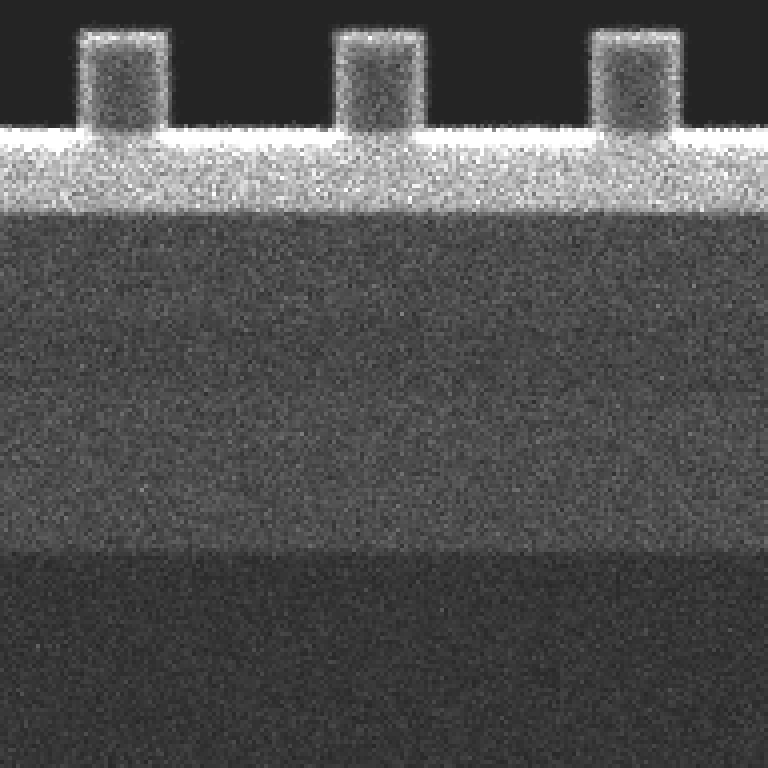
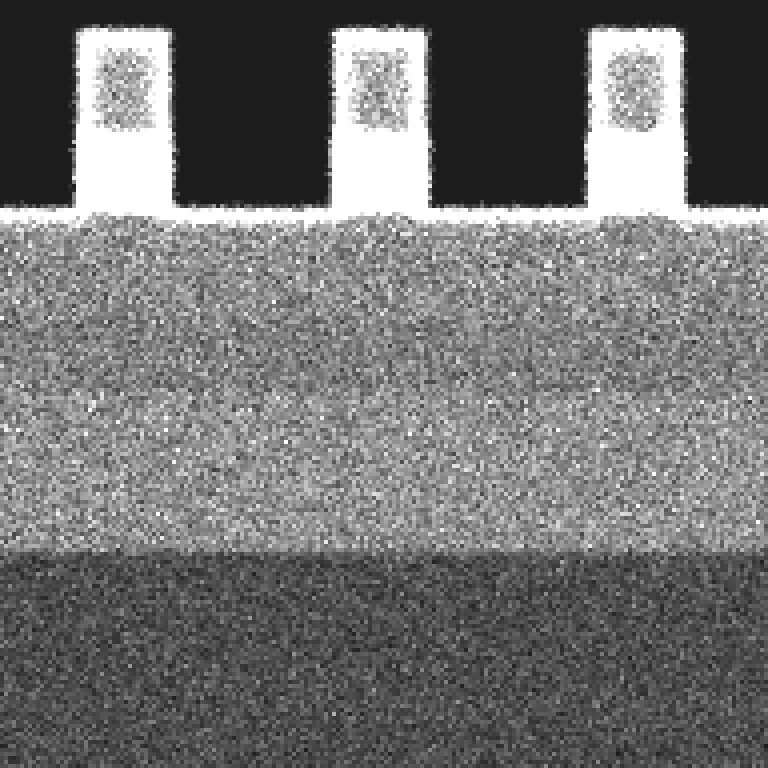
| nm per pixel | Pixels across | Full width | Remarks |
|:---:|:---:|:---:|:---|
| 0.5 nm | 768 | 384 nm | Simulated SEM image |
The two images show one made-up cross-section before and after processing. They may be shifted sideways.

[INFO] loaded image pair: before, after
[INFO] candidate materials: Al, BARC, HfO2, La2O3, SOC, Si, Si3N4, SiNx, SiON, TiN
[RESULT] removed HfO2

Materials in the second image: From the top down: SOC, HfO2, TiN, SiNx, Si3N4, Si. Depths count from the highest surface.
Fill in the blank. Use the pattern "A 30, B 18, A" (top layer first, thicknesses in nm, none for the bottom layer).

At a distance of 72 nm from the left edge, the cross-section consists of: SOC 50, HfO2 40, TiN 54, SiNx 36, Si3N4 80, Si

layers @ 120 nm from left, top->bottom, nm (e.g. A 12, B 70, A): empty 90, TiN 54, SiNx 36, Si3N4 80, Si